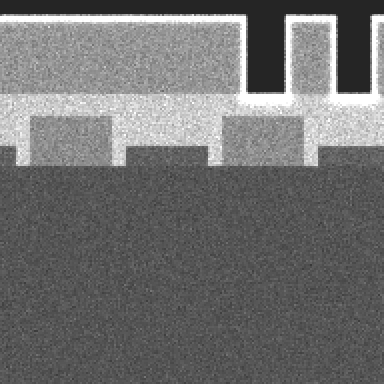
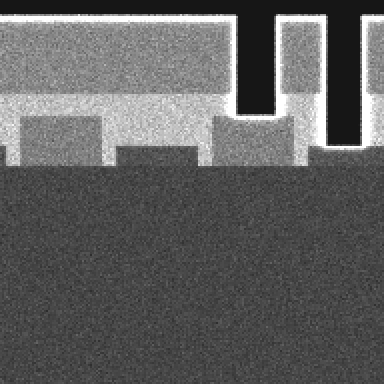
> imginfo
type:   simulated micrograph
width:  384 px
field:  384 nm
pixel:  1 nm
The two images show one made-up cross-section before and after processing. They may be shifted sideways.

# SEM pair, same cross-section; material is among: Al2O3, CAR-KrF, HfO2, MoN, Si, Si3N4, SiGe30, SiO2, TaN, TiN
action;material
removed;SiO2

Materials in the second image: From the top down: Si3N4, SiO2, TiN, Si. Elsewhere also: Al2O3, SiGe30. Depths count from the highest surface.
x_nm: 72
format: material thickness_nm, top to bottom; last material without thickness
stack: Si3N4 78, SiO2 22, TiN 50, Si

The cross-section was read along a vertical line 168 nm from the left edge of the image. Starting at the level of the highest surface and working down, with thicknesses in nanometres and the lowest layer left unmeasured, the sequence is Si3N4 78, SiO2 52, SiGe30 20, Si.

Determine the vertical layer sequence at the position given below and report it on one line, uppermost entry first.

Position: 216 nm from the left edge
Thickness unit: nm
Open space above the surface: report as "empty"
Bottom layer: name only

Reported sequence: Si3N4 78, SiO2 22, TiN 50, Si